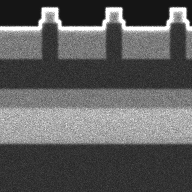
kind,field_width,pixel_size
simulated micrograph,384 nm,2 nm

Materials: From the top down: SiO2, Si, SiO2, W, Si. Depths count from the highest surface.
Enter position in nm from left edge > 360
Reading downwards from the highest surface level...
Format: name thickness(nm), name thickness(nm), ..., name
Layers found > SiO2 30, Si 132, SiO2 38, W 72, Si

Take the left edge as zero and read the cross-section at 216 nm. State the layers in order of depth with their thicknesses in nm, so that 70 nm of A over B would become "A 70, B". SiO2 30, Si 132, SiO2 38, W 72, Si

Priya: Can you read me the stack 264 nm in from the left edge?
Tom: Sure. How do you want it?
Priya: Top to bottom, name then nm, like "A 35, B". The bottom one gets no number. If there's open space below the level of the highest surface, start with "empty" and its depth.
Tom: empty 38, SiO2 64, Si 60, SiO2 38, W 72, Si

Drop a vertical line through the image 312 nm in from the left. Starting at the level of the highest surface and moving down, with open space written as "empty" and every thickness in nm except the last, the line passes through empty 38, SiO2 64, Si 60, SiO2 38, W 72, Si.